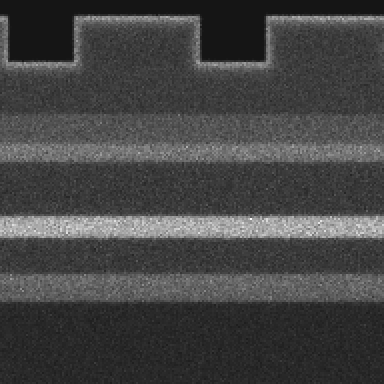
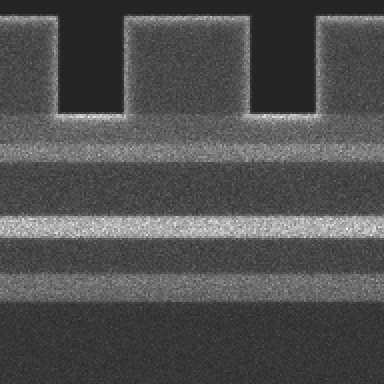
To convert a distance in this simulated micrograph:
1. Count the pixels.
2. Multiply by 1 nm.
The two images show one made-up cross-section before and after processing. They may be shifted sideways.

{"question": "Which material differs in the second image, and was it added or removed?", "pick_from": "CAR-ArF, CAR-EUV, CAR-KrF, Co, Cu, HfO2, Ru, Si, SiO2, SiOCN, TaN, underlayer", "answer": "underlayer, removed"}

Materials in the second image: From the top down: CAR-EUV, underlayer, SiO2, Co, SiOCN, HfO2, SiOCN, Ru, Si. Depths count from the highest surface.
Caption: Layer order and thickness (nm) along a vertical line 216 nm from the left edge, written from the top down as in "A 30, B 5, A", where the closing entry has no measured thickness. CAR-EUV 46, underlayer 52, SiO2 30, Co 18, SiOCN 54, HfO2 22, SiOCN 36, Ru 28, Si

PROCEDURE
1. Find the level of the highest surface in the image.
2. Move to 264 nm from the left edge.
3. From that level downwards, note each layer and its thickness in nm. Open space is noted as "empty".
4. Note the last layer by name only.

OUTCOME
empty 98, SiO2 30, Co 18, SiOCN 54, HfO2 22, SiOCN 36, Ru 28, Si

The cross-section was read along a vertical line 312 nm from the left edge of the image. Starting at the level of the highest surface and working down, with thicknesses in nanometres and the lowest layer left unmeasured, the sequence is empty 98, SiO2 30, Co 18, SiOCN 54, HfO2 22, SiOCN 36, Ru 28, Si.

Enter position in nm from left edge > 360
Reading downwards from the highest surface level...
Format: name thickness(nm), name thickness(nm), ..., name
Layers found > CAR-EUV 46, underlayer 52, SiO2 30, Co 18, SiOCN 54, HfO2 22, SiOCN 36, Ru 28, Si